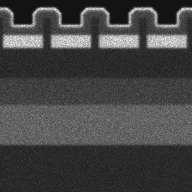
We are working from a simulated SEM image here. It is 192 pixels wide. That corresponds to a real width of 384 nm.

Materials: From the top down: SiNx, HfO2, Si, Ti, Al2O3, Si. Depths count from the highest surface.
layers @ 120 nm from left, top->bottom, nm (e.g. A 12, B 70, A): empty 10, SiNx 44, HfO2 26, Si 60, Ti 54, Al2O3 80, Si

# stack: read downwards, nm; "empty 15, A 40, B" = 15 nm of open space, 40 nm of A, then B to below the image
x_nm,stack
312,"empty 10, SiNx 44, HfO2 26, Si 60, Ti 54, Al2O3 80, Si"